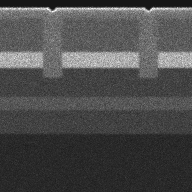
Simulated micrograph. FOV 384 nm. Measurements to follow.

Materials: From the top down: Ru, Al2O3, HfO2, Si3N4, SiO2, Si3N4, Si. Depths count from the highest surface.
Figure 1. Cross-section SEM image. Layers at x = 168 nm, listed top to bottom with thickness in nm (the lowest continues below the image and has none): Ru 22, Al2O3 66, HfO2 32, Si3N4 58, SiO2 26, Si3N4 48, Si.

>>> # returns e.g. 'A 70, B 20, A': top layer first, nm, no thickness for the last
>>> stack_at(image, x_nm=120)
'Ru 140, Si3N4 38, SiO2 26, Si3N4 48, Si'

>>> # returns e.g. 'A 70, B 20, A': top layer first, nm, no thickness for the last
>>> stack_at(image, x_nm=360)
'Ru 22, Al2O3 66, HfO2 32, Si3N4 58, SiO2 26, Si3N4 48, Si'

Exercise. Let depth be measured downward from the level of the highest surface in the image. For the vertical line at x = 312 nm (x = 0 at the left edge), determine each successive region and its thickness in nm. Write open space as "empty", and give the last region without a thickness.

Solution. Ru 140, Si3N4 38, SiO2 26, Si3N4 48, Si